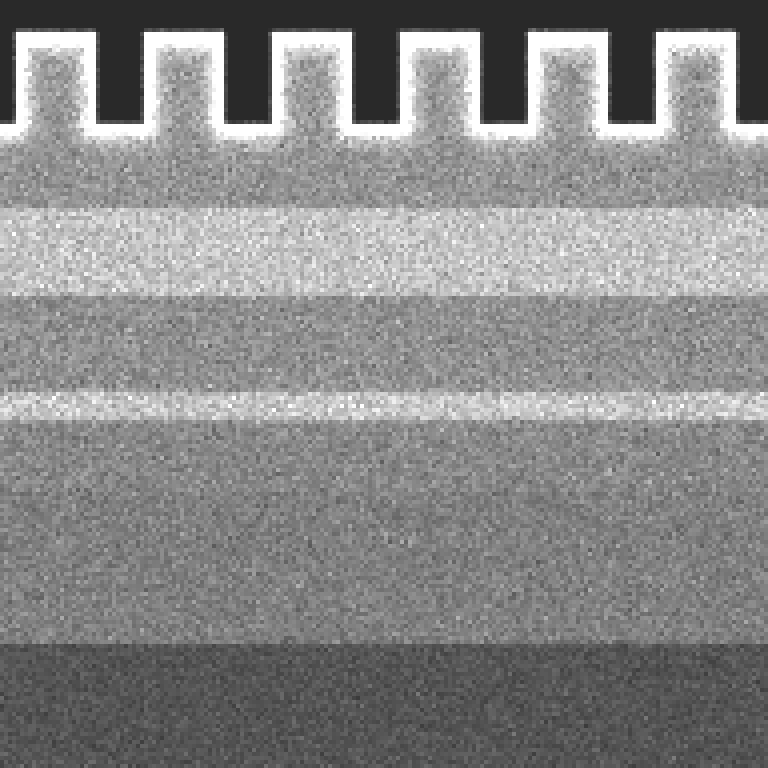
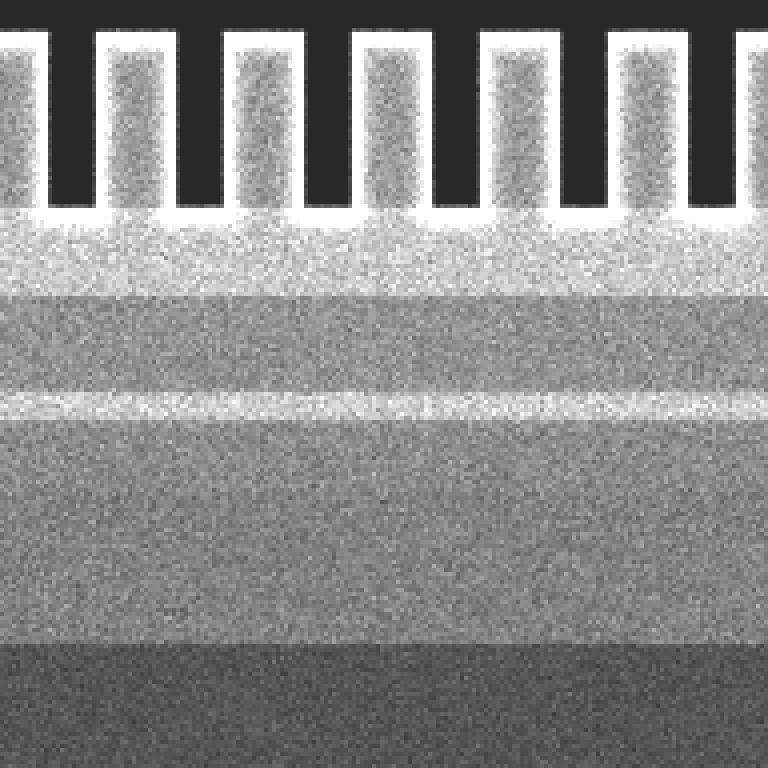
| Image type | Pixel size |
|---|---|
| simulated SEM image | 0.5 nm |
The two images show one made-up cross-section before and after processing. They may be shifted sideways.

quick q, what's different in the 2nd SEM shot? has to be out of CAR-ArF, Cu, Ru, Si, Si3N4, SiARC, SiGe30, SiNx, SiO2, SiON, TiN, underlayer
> underlayer removed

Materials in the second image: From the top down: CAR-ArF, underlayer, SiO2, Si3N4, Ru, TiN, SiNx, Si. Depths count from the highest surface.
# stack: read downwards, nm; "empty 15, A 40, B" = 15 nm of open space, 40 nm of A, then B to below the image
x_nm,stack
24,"empty 88, SiO2 44, Si3N4 48, Ru 14, TiN 36, SiNx 76, Si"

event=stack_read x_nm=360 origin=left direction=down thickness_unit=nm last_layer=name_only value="empty 88, SiO2 44, Si3N4 48, Ru 14, TiN 36, SiNx 76, Si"